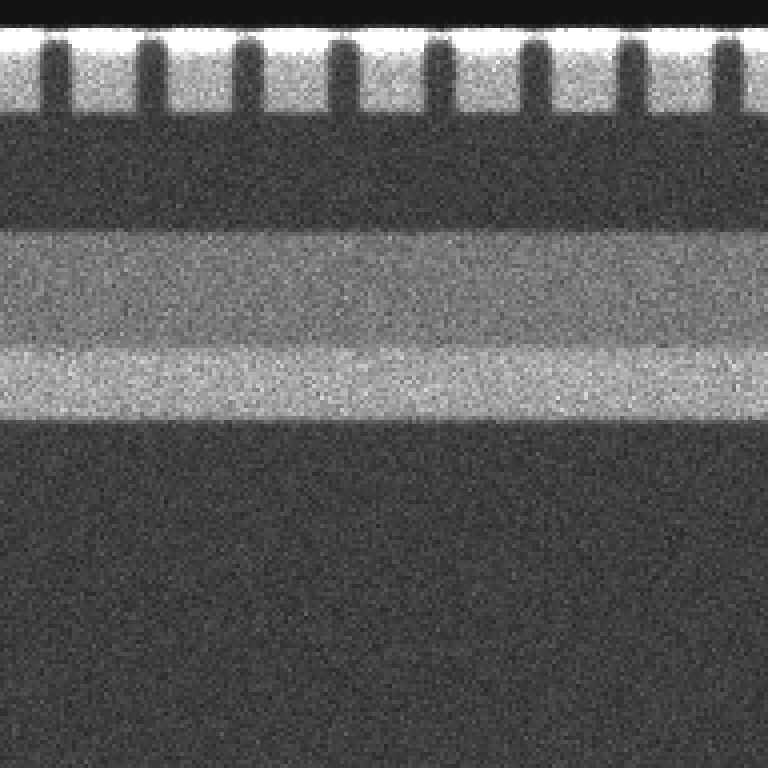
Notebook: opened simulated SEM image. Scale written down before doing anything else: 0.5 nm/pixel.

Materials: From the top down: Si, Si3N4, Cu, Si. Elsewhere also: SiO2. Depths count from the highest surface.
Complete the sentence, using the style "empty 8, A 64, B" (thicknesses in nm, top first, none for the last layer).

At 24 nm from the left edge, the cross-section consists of Si 100, Si3N4 58, Cu 36, Si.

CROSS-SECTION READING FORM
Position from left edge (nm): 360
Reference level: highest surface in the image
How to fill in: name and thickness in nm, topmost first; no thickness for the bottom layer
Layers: Si 100, Si3N4 58, Cu 36, Si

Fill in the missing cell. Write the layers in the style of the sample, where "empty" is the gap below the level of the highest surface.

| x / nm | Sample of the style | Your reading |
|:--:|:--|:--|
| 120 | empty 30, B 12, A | Si 100, Si3N4 58, Cu 36, Si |